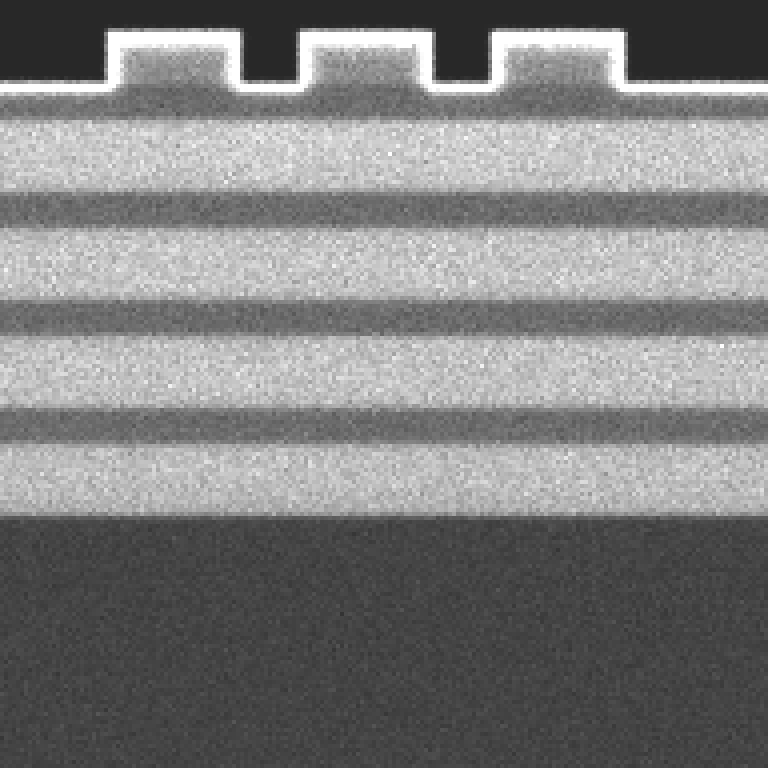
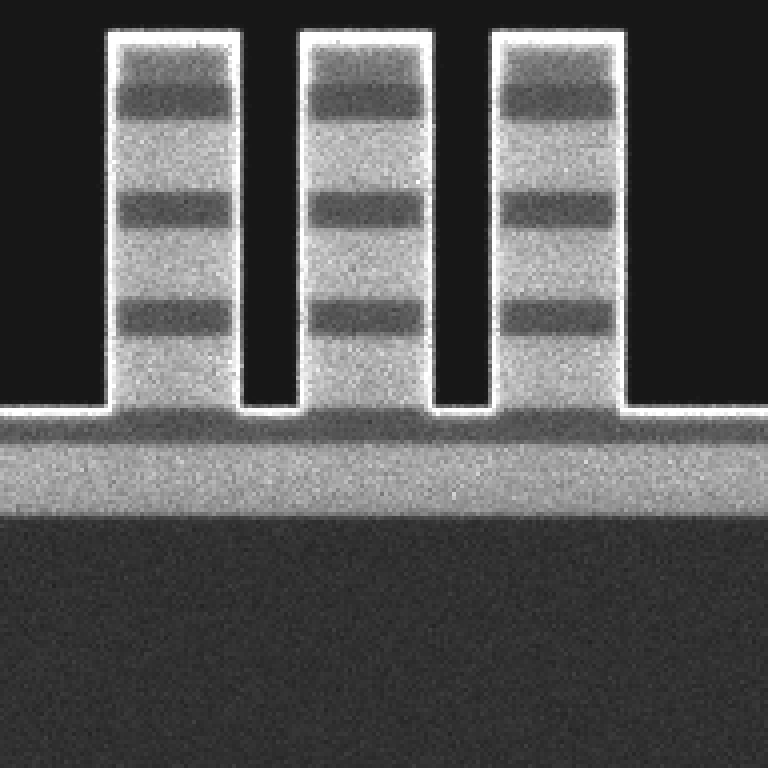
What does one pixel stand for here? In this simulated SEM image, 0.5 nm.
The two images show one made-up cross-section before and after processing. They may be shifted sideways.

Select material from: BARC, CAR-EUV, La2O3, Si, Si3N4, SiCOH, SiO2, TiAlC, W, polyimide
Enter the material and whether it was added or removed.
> Si3N4 and W / removed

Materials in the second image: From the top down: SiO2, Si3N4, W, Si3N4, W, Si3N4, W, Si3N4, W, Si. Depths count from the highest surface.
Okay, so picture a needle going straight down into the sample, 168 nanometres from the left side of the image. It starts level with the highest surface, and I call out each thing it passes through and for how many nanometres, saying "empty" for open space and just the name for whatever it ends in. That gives SiO2 26, Si3N4 18, W 36, Si3N4 18, W 36, Si3N4 18, W 36, Si3N4 18, W 36, Si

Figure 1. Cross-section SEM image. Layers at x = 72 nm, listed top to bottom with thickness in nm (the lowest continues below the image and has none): SiO2 26, Si3N4 18, W 36, Si3N4 18, W 36, Si3N4 18, W 36, Si3N4 18, W 36, Si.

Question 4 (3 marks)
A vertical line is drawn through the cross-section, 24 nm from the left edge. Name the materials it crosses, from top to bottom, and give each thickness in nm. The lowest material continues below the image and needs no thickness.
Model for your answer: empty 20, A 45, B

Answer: empty 188, Si3N4 18, W 36, Si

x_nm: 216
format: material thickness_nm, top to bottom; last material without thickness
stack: empty 188, Si3N4 18, W 36, Si